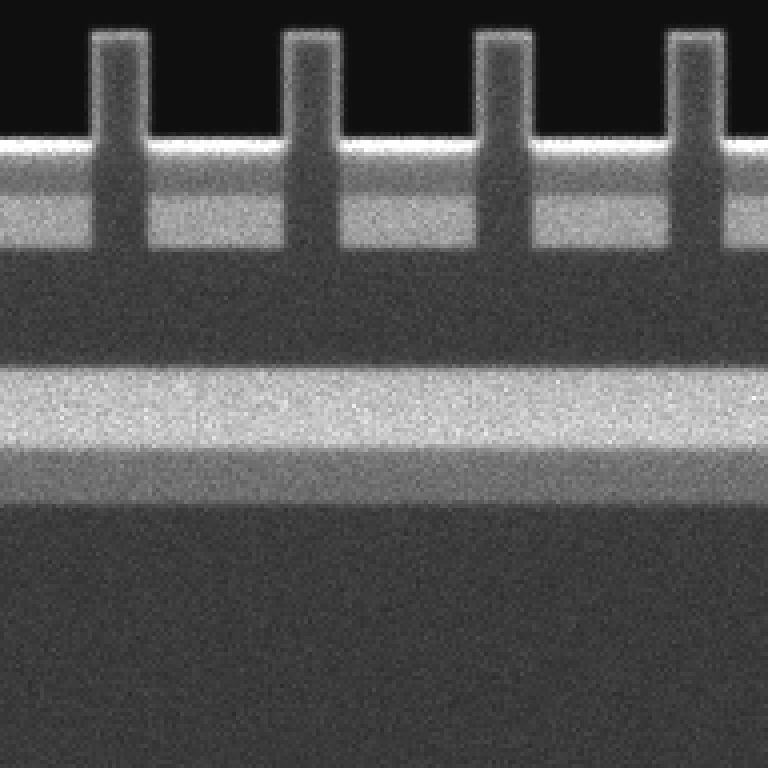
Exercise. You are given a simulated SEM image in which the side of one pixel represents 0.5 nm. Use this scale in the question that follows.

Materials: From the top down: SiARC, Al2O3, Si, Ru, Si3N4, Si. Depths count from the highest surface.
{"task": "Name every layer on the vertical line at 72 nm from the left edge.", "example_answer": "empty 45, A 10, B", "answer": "Si 168, Ru 40, Si3N4 28, Si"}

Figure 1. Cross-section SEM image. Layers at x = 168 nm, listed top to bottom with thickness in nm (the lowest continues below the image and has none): Si 168, Ru 40, Si3N4 28, Si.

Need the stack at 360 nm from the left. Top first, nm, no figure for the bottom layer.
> Si 168, Ru 40, Si3N4 28, Si